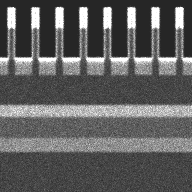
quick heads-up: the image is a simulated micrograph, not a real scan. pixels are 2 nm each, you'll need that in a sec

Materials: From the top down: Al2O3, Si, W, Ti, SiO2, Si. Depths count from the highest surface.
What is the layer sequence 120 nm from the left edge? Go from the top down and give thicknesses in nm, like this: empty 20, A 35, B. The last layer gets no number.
Al2O3 40, Si 154, W 24, Ti 42, SiO2 28, Si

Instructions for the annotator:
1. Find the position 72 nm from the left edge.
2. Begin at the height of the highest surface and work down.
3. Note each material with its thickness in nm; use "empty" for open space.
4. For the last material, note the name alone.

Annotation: Al2O3 40, Si 154, W 24, Ti 42, SiO2 28, Si